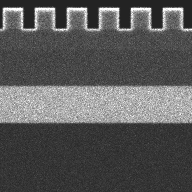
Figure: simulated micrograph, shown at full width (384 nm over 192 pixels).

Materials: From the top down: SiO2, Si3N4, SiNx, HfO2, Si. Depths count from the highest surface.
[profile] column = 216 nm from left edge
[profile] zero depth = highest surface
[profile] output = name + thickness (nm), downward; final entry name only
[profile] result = SiO2 42, Si3N4 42, SiNx 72, HfO2 74, Si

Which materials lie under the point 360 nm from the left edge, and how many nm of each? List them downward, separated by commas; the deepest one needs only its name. SiO2 42, Si3N4 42, SiNx 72, HfO2 74, Si